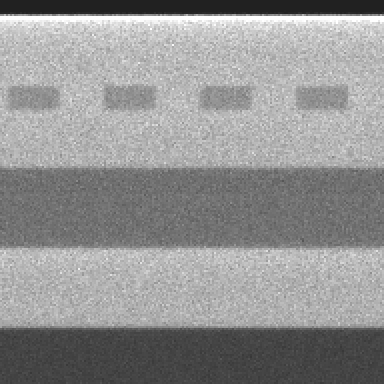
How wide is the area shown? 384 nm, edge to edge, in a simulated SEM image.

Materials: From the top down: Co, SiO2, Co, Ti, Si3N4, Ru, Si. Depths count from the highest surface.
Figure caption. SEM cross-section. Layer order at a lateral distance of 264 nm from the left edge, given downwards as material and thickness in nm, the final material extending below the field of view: Co 152, Ti 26, Si3N4 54, Ru 80, Si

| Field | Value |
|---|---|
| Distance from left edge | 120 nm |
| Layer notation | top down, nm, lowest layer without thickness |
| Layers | Co 70, SiO2 24, Co 58, Ti 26, Si3N4 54, Ru 80, Si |